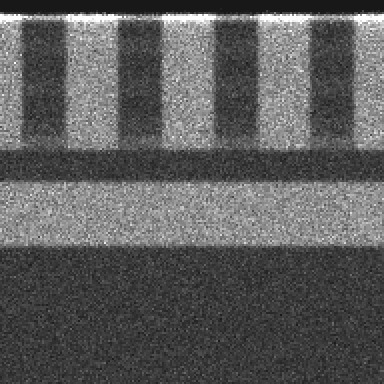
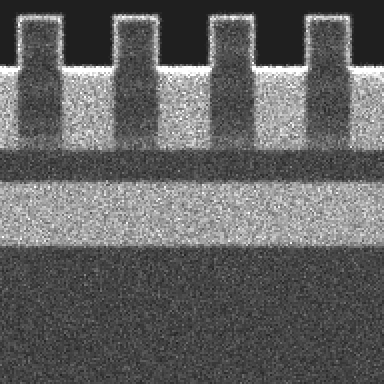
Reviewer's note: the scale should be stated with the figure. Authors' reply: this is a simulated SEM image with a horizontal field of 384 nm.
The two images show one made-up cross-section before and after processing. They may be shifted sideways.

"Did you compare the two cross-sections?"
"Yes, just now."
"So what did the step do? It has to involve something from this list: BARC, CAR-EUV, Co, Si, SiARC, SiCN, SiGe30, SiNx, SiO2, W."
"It removed Co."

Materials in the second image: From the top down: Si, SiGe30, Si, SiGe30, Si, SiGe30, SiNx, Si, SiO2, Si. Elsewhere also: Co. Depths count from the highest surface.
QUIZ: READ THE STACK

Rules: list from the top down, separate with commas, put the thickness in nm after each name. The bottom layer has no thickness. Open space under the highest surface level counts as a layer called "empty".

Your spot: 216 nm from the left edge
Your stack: Si 22, SiGe30 18, Si 22, SiGe30 18, Si 22, SiGe30 18, SiNx 14, Si 32, SiO2 64, Si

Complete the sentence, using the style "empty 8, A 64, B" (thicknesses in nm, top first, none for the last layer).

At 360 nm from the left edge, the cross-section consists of empty 52, Co 82, Si 32, SiO2 64, Si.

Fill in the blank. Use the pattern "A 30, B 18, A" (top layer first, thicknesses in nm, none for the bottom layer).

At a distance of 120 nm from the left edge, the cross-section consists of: Si 22, SiGe30 18, Si 22, SiGe30 18, Si 22, SiGe30 18, SiNx 14, Si 32, SiO2 64, Si